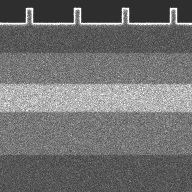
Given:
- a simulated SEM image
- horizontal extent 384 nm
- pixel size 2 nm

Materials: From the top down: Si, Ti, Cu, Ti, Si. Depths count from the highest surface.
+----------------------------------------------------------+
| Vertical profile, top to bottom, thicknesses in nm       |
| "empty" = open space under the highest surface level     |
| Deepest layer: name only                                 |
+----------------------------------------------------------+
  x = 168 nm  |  empty 30, Si 60, Ti 62, Cu 56, Ti 86, Si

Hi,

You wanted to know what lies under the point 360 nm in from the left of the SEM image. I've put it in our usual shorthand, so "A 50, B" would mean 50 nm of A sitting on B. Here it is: empty 30, Si 60, Ti 62, Cu 56, Ti 86, Si